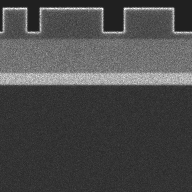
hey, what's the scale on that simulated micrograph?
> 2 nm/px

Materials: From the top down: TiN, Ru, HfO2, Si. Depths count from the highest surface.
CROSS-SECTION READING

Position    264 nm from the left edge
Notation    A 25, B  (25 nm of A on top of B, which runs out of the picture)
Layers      TiN 62, Ru 68, HfO2 24, Si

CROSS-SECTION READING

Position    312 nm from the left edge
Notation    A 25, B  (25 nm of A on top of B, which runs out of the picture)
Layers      TiN 62, Ru 68, HfO2 24, Si